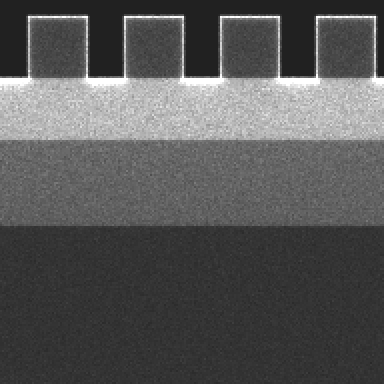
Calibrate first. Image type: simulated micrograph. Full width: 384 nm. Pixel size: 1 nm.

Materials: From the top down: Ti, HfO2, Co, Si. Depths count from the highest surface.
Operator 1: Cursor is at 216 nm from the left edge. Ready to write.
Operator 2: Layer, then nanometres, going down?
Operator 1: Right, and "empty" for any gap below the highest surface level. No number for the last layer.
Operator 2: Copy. empty 62, HfO2 62, Co 86, Si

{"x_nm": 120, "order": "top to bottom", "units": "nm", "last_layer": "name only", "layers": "empty 62, HfO2 62, Co 86, Si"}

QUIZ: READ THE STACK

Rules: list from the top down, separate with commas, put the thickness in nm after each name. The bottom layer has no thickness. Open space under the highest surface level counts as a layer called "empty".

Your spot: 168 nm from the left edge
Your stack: Ti 62, HfO2 62, Co 86, Si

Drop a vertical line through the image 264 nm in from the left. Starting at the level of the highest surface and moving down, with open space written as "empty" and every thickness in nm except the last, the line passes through Ti 62, HfO2 62, Co 86, Si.